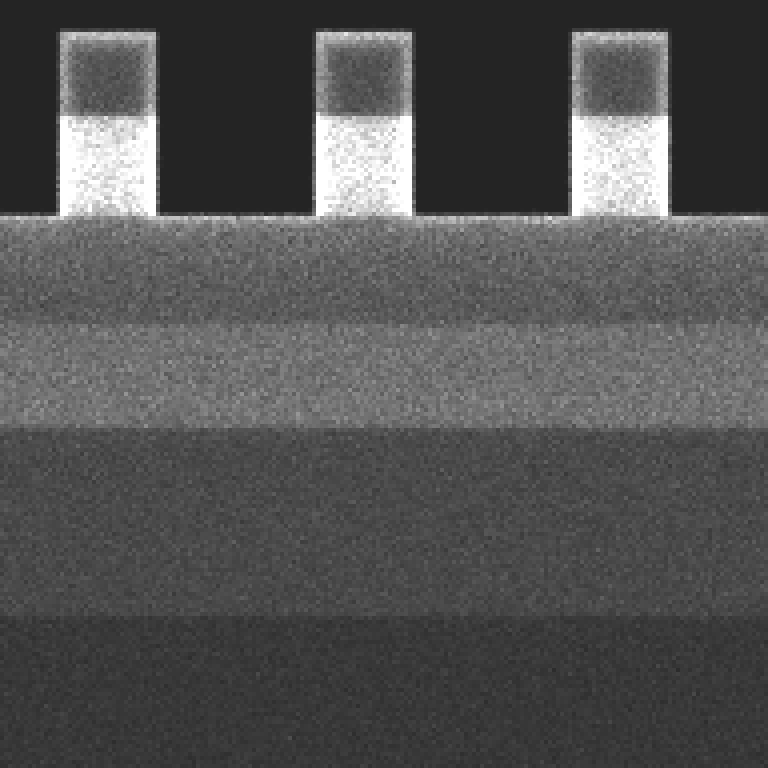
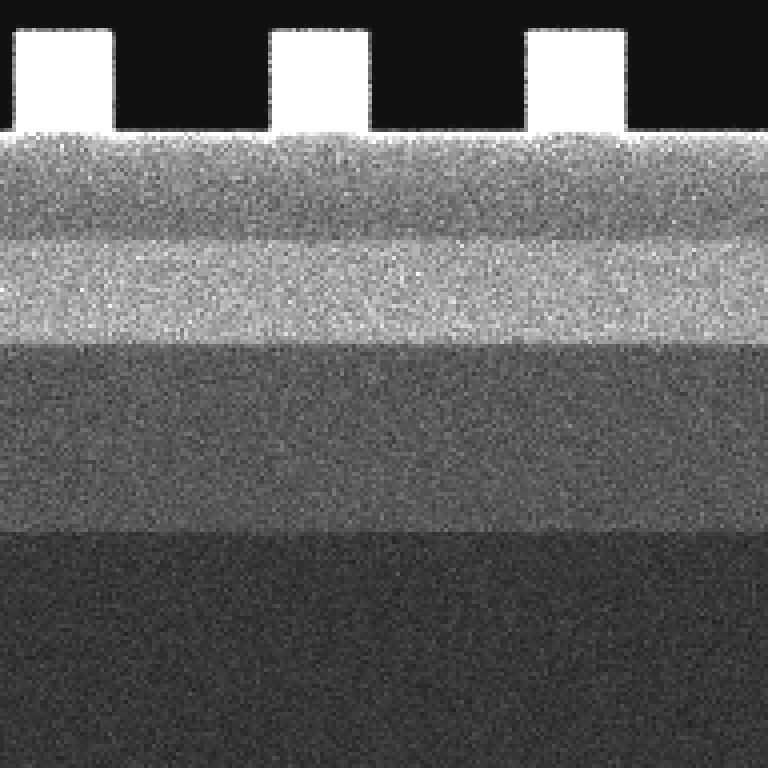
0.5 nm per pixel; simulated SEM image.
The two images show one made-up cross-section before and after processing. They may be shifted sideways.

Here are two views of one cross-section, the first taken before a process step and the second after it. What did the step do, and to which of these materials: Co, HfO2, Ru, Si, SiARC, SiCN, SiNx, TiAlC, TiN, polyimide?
It removed SiARC.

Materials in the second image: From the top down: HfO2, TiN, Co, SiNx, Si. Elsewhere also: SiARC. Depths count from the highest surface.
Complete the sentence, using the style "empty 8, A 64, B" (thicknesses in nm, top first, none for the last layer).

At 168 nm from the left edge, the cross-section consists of HfO2 50, TiN 54, Co 52, SiNx 94, Si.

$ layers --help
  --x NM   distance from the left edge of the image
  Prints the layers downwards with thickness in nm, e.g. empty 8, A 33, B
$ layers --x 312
empty 50, TiN 54, Co 52, SiNx 94, Si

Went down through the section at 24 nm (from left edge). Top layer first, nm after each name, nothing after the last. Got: HfO2 50, TiN 54, Co 52, SiNx 94, Si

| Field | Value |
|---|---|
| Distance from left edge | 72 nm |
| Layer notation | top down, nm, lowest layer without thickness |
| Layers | empty 50, TiN 54, Co 52, SiNx 94, Si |